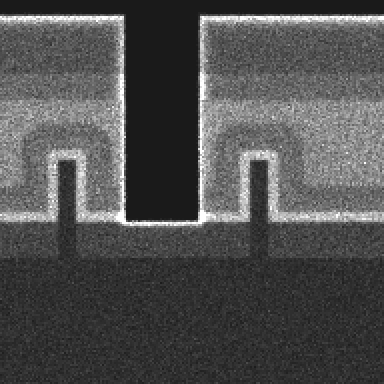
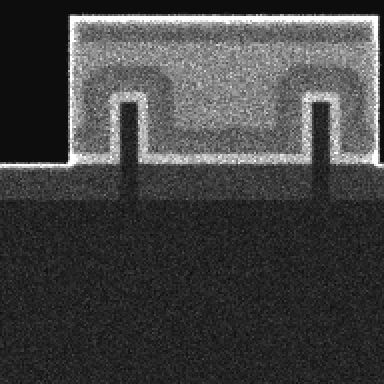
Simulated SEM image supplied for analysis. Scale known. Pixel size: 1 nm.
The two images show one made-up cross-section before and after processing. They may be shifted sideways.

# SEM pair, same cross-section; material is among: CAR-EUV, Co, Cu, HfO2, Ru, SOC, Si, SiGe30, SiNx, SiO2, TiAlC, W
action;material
removed;SOC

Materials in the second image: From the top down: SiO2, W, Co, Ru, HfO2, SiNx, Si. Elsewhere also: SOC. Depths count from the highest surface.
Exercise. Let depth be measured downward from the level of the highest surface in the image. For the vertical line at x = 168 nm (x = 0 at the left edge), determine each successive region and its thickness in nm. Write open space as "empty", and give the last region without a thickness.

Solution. SiO2 26, W 36, Co 62, Ru 14, HfO2 10, SiNx 36, Si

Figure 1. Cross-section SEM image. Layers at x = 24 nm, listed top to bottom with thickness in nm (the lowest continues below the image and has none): empty 148, SiNx 36, Si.